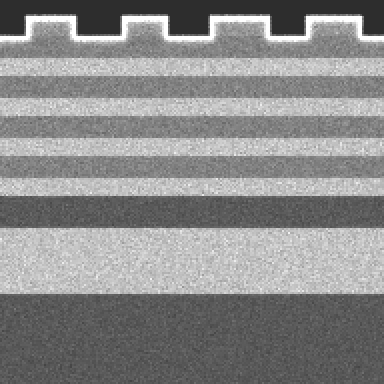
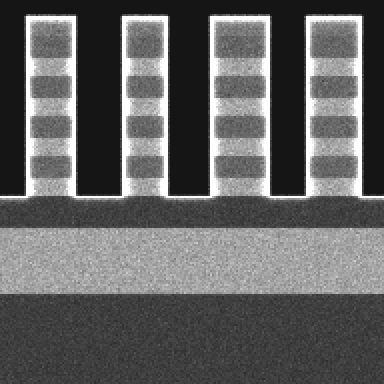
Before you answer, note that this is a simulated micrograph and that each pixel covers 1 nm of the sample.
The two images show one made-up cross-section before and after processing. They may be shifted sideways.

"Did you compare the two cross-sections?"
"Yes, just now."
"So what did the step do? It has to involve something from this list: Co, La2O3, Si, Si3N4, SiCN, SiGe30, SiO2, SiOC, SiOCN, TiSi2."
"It removed SiO2 and SiOCN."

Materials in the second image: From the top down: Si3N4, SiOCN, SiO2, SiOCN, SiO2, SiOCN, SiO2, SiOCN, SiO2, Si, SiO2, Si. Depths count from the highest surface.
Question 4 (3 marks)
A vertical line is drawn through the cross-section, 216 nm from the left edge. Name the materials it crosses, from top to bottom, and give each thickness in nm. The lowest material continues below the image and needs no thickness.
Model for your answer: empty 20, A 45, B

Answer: Si3N4 20, SiOCN 22, SiO2 18, SiOCN 22, SiO2 18, SiOCN 22, SiO2 18, SiOCN 22, SiO2 18, Si 32, SiO2 66, Si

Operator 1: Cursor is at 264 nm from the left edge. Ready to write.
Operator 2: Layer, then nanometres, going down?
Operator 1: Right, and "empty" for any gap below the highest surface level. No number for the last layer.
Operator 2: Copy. Si3N4 20, SiOCN 22, SiO2 18, SiOCN 22, SiO2 18, SiOCN 22, SiO2 18, SiOCN 22, SiO2 18, Si 32, SiO2 66, Si